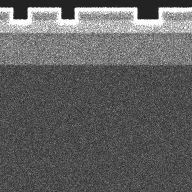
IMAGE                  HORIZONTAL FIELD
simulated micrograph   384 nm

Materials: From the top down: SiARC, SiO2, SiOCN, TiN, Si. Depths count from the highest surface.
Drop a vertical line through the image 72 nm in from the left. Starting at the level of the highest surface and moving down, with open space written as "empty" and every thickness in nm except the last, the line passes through SiARC 24, SiO2 26, SiOCN 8, TiN 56, Si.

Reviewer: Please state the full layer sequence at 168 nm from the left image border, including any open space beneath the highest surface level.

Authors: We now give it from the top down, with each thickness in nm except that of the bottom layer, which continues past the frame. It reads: SiARC 24, SiO2 26, SiOCN 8, TiN 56, Si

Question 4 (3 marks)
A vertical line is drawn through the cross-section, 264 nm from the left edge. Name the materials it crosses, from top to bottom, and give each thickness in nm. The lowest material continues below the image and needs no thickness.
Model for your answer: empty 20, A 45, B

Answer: SiARC 24, SiO2 26, SiOCN 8, TiN 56, Si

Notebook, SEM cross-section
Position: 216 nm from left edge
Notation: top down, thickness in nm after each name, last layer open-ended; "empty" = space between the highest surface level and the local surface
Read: SiARC 24, SiO2 26, SiOCN 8, TiN 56, Si